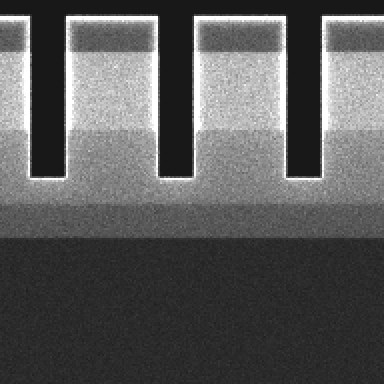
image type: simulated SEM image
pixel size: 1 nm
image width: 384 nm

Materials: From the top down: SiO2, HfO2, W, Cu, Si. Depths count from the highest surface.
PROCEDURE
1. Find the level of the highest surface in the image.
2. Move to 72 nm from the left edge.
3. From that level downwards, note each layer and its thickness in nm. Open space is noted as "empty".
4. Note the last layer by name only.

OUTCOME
SiO2 36, HfO2 78, W 74, Cu 34, Si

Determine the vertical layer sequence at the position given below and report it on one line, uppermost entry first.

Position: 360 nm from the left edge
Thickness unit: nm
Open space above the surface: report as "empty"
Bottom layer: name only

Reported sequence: SiO2 36, HfO2 78, W 74, Cu 34, Si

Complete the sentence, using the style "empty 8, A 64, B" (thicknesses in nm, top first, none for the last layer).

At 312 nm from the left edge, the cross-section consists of empty 162, W 26, Cu 34, Si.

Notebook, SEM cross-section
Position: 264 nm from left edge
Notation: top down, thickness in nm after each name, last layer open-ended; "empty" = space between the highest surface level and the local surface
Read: SiO2 36, HfO2 78, W 74, Cu 34, Si